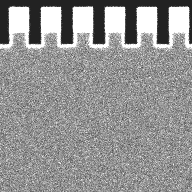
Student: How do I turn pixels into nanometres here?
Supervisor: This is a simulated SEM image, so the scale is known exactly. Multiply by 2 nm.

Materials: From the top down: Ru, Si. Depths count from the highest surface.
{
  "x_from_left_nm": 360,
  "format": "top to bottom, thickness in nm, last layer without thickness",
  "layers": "Ru 48, Si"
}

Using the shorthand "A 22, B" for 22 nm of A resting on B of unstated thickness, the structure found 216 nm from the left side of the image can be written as Ru 48, Si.